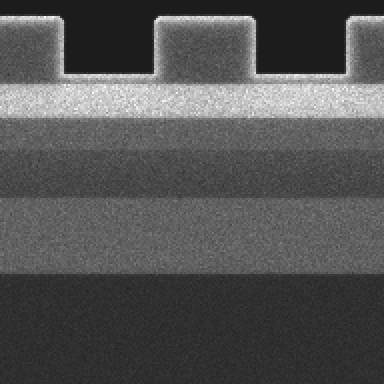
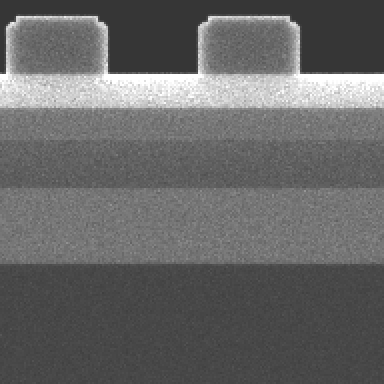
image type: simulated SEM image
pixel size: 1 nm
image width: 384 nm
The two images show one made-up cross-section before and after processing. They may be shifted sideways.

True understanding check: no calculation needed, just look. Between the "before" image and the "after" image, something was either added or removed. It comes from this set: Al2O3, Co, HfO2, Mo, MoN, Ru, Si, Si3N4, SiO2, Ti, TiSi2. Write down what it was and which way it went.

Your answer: SiO2 (removed)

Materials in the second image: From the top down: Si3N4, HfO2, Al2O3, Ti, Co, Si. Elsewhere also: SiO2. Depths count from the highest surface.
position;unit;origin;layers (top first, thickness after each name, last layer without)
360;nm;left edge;empty 58, HfO2 34, Al2O3 32, Ti 48, Co 76, Si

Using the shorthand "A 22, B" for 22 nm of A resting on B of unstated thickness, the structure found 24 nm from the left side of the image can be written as Si3N4 58, HfO2 34, Al2O3 32, Ti 48, Co 76, Si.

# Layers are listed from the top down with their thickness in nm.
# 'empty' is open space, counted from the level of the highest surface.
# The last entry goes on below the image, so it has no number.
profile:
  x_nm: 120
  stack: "empty 58, HfO2 34, Al2O3 32, Ti 48, Co 76, Si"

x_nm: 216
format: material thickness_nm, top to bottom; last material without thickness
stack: Si3N4 58, HfO2 34, Al2O3 32, Ti 48, Co 76, Si